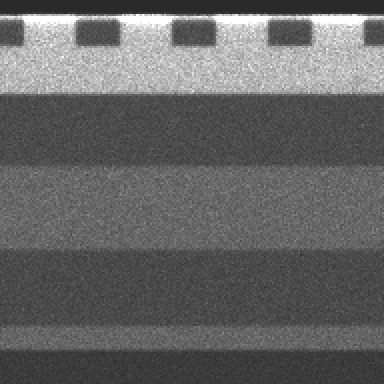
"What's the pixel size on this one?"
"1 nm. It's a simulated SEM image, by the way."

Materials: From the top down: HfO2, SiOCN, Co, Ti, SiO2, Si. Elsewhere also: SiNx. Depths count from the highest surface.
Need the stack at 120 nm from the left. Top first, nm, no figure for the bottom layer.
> HfO2 78, SiOCN 72, Co 84, Ti 76, SiO2 24, Si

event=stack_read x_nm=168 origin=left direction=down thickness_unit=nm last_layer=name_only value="HfO2 78, SiOCN 72, Co 84, Ti 76, SiO2 24, Si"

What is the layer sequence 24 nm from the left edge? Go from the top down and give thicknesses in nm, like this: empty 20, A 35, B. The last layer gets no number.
HfO2 78, SiOCN 72, Co 84, Ti 76, SiO2 24, Si